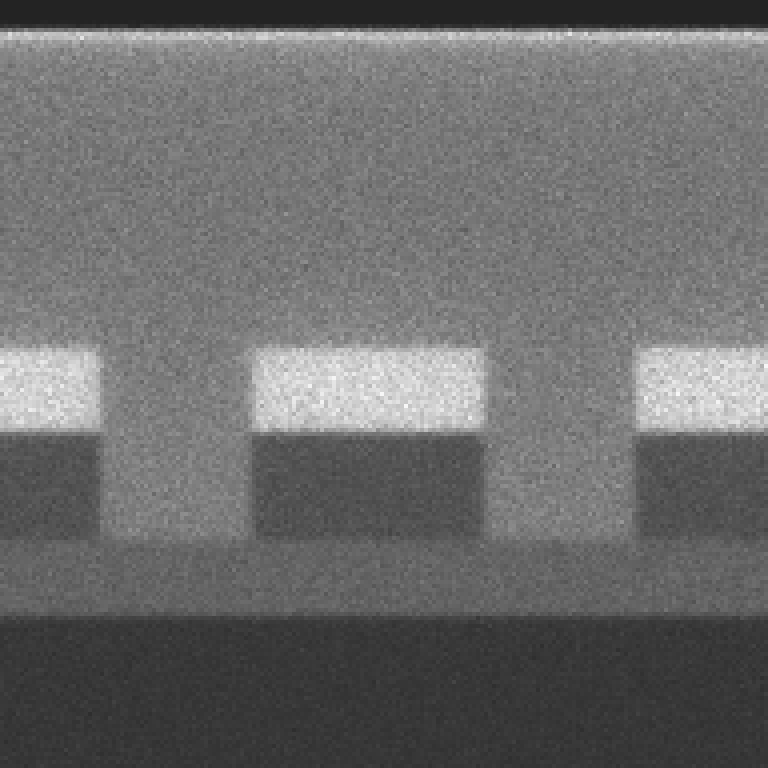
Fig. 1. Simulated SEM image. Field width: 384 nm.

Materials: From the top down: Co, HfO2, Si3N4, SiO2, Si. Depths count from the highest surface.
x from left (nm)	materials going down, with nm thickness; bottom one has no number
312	Co 254, SiO2 38, Si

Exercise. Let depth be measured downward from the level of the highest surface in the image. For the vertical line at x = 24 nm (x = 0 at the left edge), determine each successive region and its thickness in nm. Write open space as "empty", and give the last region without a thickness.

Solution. Co 158, HfO2 42, Si3N4 54, SiO2 38, Si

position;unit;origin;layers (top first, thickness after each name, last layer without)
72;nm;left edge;Co 254, SiO2 38, Si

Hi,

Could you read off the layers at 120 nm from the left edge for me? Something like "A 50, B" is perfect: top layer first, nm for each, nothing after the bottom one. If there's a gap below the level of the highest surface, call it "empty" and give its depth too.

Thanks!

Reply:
Co 254, SiO2 38, Si